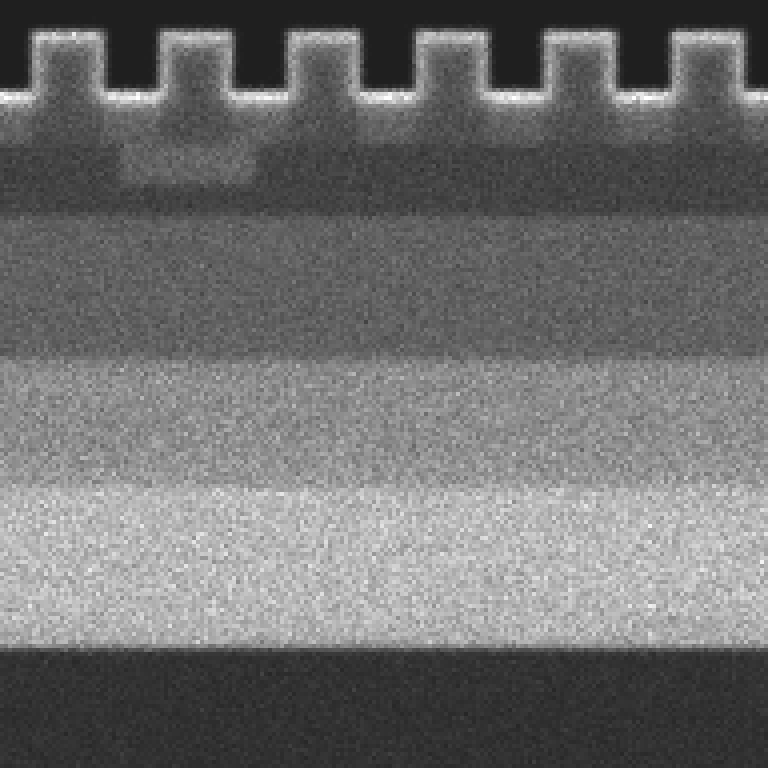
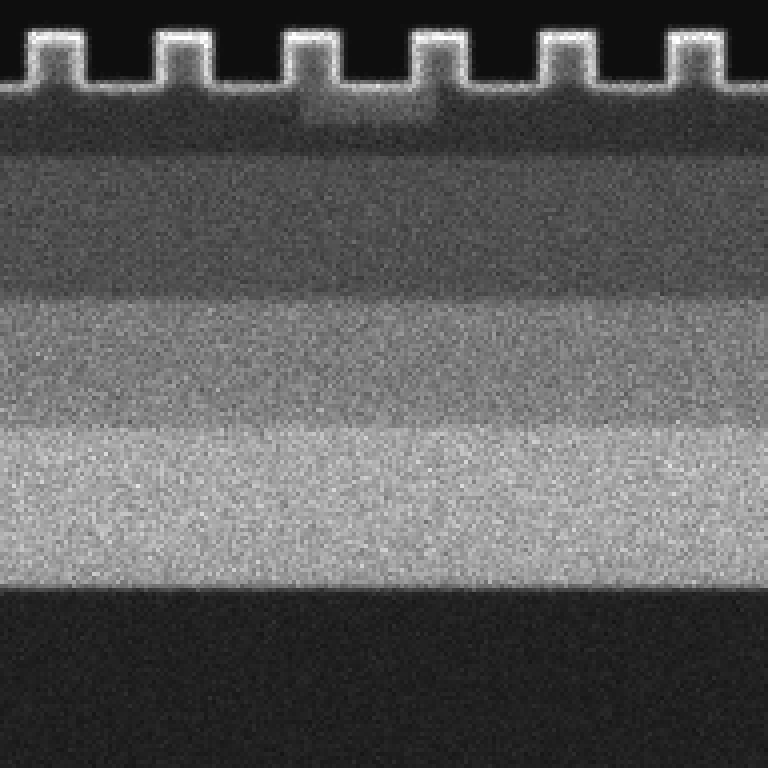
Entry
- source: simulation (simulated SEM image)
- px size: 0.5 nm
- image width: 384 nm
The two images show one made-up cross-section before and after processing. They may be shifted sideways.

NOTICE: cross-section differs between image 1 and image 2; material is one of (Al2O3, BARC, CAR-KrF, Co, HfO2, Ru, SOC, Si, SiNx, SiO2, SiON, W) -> removed: SOC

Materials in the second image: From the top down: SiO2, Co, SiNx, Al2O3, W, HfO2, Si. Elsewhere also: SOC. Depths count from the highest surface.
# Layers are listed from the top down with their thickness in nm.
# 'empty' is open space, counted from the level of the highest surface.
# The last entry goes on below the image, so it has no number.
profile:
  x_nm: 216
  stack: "SiO2 26, Co 20, SiNx 16, Al2O3 72, W 64, HfO2 80, Si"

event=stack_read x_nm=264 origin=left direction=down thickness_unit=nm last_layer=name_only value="empty 26, SiNx 36, Al2O3 72, W 64, HfO2 80, Si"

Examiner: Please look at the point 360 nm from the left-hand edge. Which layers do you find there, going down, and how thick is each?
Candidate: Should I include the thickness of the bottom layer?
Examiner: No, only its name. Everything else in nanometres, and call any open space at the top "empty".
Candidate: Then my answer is SiO2 26, SiNx 36, Al2O3 72, W 64, HfO2 80, Si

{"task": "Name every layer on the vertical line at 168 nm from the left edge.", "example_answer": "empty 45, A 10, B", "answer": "SiO2 26, Co 20, SiNx 16, Al2O3 72, W 64, HfO2 80, Si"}